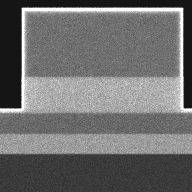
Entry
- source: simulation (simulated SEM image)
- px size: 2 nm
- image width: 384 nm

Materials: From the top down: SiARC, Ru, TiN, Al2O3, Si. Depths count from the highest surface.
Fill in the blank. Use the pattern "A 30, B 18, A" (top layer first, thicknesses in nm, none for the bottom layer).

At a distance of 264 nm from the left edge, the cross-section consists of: SiARC 138, Ru 72, TiN 42, Al2O3 40, Si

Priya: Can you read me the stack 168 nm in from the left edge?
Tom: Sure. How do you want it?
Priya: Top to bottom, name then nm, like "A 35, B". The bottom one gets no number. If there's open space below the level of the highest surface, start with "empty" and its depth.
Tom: SiARC 138, Ru 72, TiN 42, Al2O3 40, Si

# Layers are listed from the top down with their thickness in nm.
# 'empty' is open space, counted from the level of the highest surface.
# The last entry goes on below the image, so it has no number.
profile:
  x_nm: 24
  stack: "empty 202, Ru 8, TiN 42, Al2O3 40, Si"